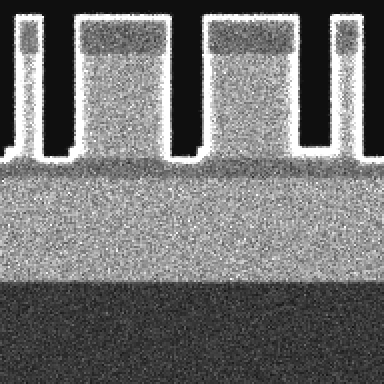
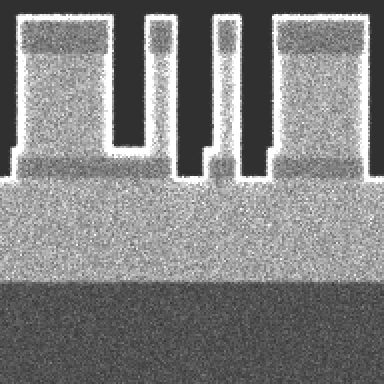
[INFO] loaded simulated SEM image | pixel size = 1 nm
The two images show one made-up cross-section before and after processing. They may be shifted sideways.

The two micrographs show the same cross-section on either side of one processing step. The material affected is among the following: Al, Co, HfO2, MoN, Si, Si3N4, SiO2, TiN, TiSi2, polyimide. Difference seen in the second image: Si3N4 removed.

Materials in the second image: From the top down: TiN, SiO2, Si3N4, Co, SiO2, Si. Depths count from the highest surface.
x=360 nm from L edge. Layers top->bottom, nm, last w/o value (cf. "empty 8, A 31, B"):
TiN 38, SiO2 104, Si3N4 20, SiO2 104, Si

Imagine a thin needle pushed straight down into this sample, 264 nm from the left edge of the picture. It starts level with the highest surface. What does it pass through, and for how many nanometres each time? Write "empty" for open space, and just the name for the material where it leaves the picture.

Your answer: empty 162, Co 72, SiO2 32, Si